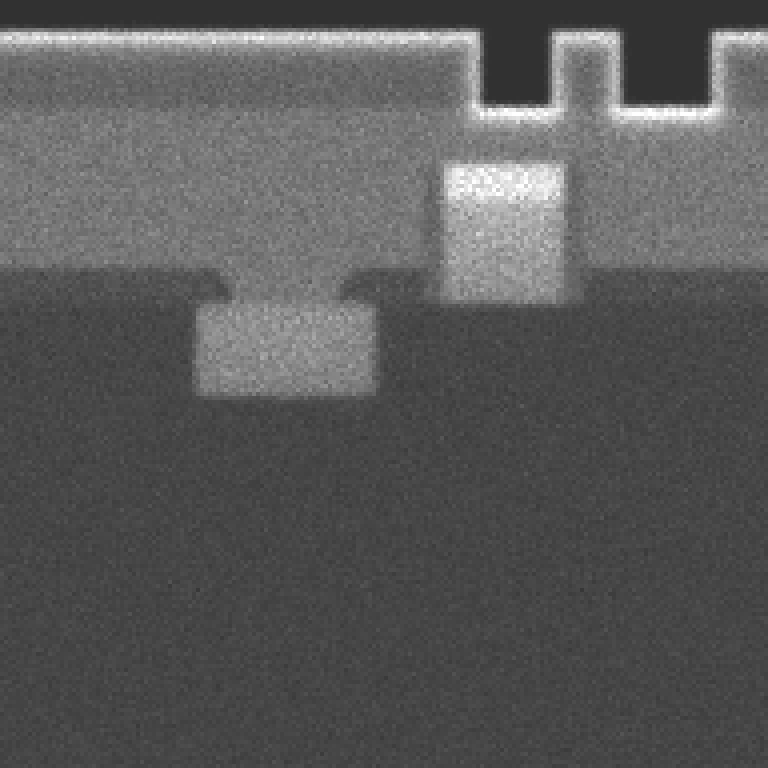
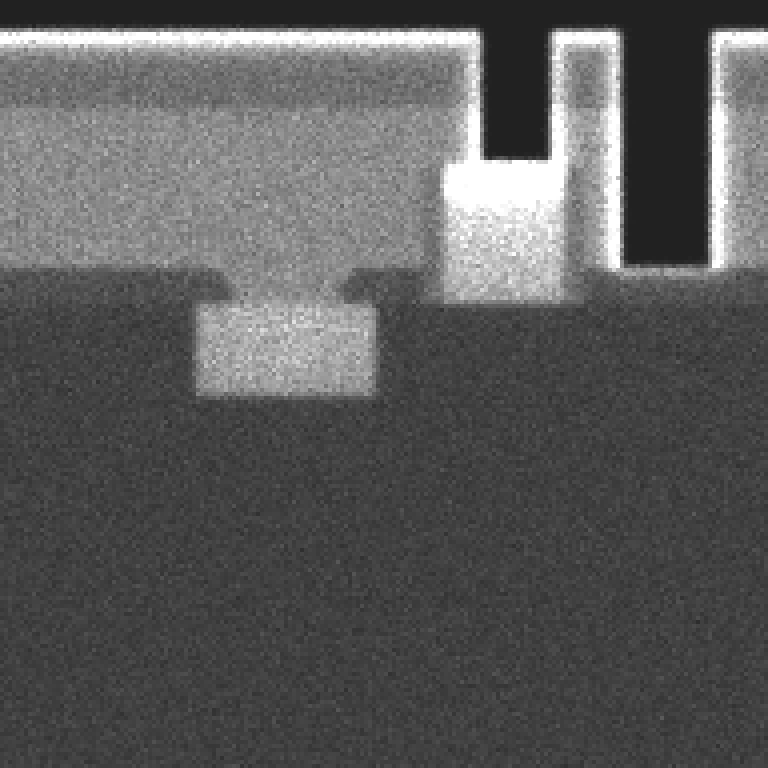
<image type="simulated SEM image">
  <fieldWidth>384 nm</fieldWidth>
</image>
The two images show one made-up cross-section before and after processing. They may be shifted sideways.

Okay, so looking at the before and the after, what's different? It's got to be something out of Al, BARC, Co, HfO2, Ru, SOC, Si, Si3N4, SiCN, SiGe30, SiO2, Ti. SiO2, removed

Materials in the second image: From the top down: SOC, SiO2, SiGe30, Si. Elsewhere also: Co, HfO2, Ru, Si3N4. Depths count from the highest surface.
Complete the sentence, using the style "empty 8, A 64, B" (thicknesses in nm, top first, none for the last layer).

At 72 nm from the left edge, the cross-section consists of SOC 38, SiO2 80, SiGe30 18, Si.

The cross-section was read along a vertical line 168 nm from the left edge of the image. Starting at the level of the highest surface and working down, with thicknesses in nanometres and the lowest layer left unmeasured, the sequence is SOC 38, SiO2 98, Co 46, Si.